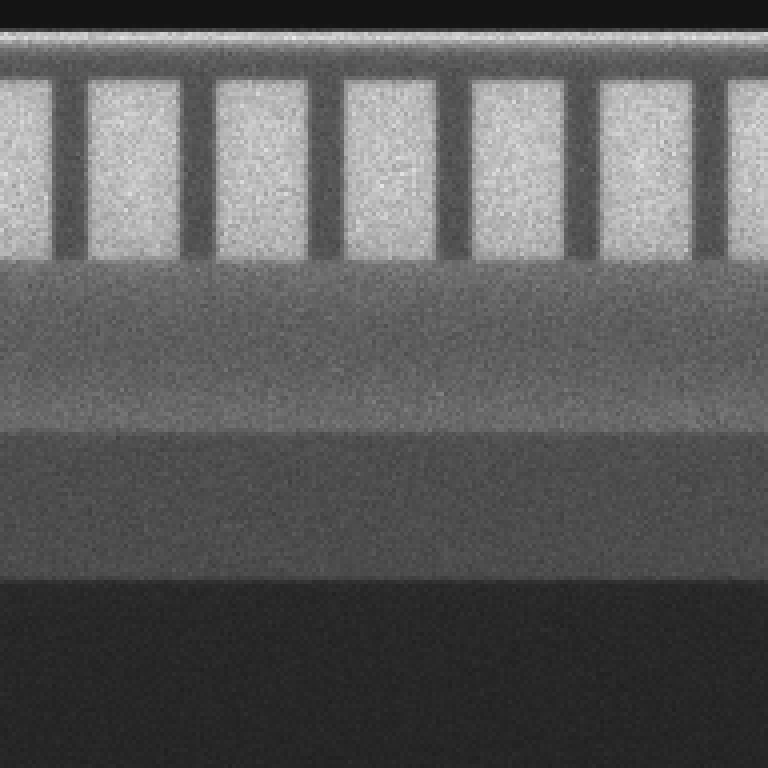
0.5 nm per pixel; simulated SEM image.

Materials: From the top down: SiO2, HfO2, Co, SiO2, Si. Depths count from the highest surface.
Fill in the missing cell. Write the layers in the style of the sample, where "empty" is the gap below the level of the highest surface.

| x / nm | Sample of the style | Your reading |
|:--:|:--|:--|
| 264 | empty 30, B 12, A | SiO2 24, HfO2 90, Co 86, SiO2 74, Si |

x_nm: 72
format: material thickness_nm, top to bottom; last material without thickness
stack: SiO2 24, HfO2 90, Co 86, SiO2 74, Si